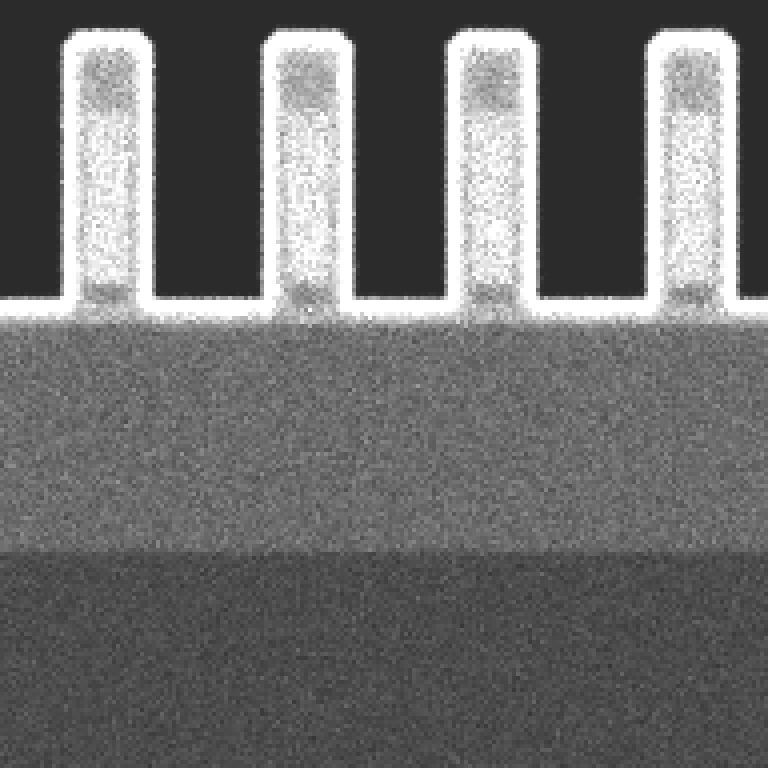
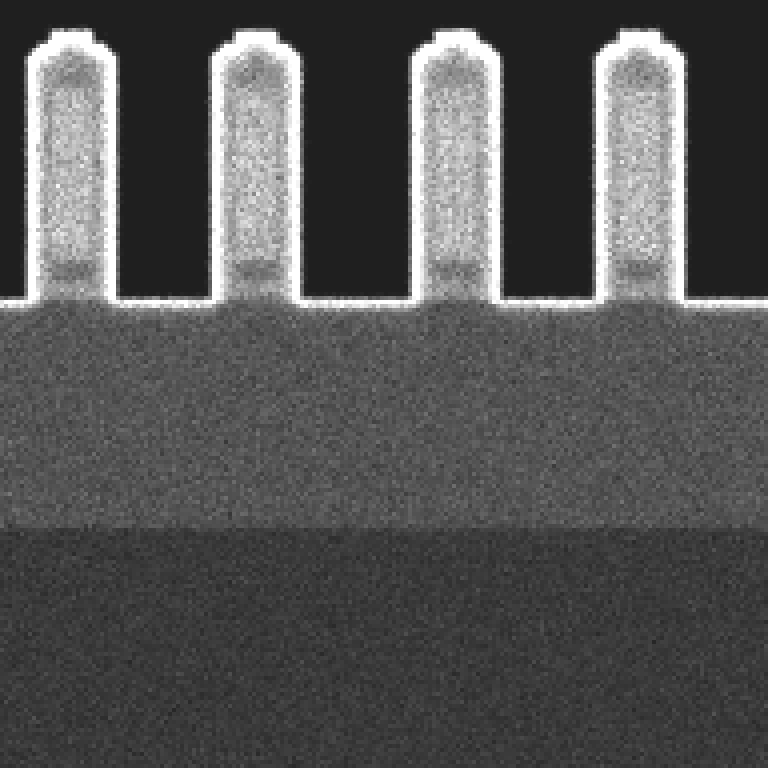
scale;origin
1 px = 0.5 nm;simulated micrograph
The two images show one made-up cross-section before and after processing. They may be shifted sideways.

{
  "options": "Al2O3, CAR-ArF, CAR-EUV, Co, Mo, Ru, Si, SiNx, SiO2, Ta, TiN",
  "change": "removed",
  "material": "SiO2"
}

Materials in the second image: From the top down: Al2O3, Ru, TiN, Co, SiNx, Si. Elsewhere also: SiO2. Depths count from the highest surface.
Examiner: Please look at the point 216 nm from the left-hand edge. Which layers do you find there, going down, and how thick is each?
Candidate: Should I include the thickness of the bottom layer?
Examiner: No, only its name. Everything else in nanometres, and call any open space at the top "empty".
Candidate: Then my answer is empty 6, SiO2 128, SiNx 114, Si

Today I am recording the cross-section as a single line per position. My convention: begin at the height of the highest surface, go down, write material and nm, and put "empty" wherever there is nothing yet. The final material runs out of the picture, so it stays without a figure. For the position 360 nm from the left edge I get empty 134, SiNx 114, Si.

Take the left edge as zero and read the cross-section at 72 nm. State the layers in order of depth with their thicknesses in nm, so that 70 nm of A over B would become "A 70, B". empty 134, SiNx 114, Si